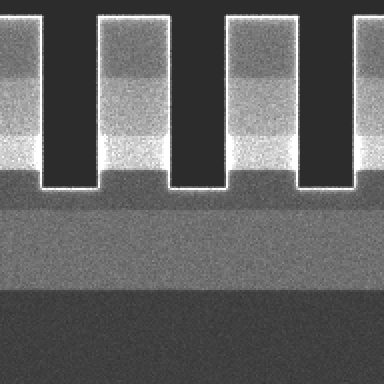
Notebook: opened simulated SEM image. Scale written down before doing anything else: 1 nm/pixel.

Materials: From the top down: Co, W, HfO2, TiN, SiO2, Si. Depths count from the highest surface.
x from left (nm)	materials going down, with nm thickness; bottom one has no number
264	Co 62, W 58, HfO2 34, TiN 40, SiO2 80, Si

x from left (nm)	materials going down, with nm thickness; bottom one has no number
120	Co 62, W 58, HfO2 34, TiN 40, SiO2 80, Si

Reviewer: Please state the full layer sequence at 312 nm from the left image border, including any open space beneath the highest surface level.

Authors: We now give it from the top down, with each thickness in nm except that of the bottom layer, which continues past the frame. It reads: empty 172, TiN 22, SiO2 80, Si